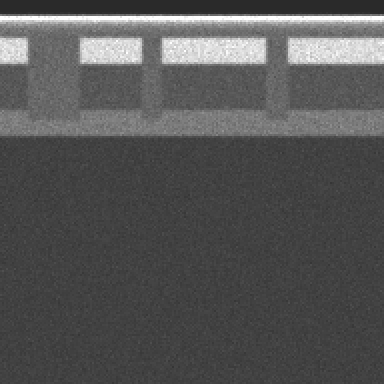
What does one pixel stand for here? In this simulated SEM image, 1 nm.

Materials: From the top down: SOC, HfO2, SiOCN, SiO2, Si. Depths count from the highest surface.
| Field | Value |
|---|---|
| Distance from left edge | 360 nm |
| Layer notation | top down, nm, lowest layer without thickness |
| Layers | SOC 22, HfO2 26, SiOCN 46, SiO2 26, Si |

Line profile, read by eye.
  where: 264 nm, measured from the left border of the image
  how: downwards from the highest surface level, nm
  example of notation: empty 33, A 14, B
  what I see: SOC 22, HfO2 26, SiOCN 46, SiO2 26, Si